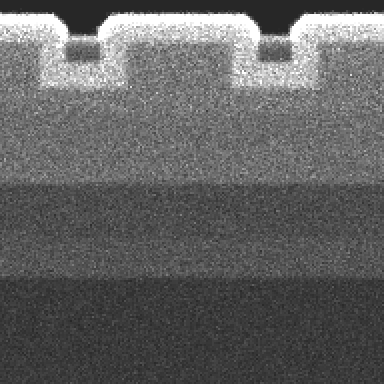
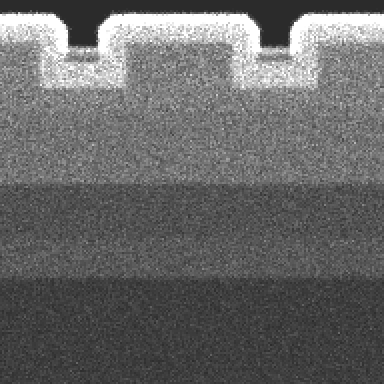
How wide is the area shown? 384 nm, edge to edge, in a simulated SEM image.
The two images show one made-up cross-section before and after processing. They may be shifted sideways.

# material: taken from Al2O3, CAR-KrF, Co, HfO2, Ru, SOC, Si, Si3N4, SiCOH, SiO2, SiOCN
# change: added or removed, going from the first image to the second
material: SOC
change: removed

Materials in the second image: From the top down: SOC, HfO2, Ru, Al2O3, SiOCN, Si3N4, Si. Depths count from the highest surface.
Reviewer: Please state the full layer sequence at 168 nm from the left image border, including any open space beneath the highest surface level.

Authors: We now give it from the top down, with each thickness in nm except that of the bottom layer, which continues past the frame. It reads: HfO2 26, Ru 72, Al2O3 70, SiOCN 54, Si3N4 40, Si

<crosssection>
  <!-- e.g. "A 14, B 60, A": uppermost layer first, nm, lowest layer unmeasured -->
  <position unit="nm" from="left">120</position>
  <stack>HfO2 72, Ru 26, Al2O3 70, SiOCN 54, Si3N4 40, Si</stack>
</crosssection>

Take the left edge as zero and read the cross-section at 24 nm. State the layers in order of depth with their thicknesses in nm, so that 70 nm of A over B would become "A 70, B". HfO2 26, Ru 72, Al2O3 70, SiOCN 54, Si3N4 40, Si